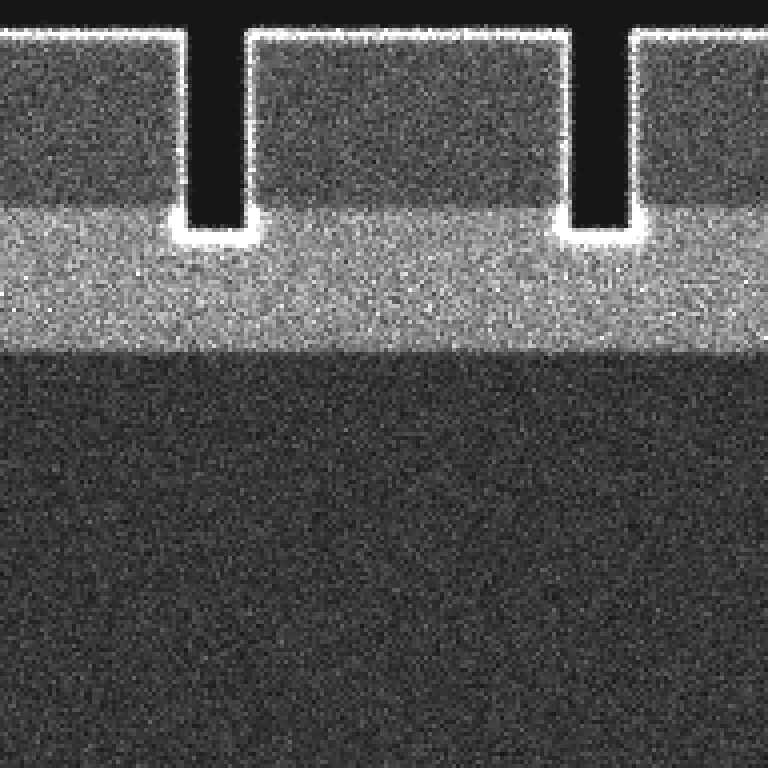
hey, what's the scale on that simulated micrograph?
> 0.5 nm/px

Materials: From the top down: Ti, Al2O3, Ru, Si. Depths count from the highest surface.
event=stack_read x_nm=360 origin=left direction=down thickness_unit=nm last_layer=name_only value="Ti 88, Al2O3 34, Ru 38, Si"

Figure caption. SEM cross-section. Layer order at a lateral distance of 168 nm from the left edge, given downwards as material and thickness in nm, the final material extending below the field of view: Ti 88, Al2O3 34, Ru 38, Si